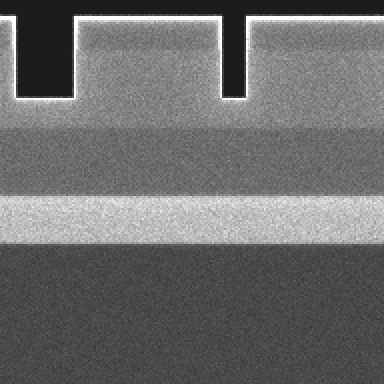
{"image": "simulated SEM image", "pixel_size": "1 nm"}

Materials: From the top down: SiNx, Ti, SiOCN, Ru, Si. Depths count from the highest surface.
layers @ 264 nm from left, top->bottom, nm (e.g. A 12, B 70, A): SiNx 34, Ti 78, SiOCN 68, Ru 48, Si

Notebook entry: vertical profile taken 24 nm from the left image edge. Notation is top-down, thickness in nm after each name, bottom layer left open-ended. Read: empty 82, Ti 30, SiOCN 68, Ru 48, Si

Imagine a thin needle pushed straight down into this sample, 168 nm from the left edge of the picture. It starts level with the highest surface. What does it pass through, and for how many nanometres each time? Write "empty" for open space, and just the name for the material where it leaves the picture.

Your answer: SiNx 34, Ti 78, SiOCN 68, Ru 48, Si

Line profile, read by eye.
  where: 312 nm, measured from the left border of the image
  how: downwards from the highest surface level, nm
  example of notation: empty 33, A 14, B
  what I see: SiNx 34, Ti 78, SiOCN 68, Ru 48, Si